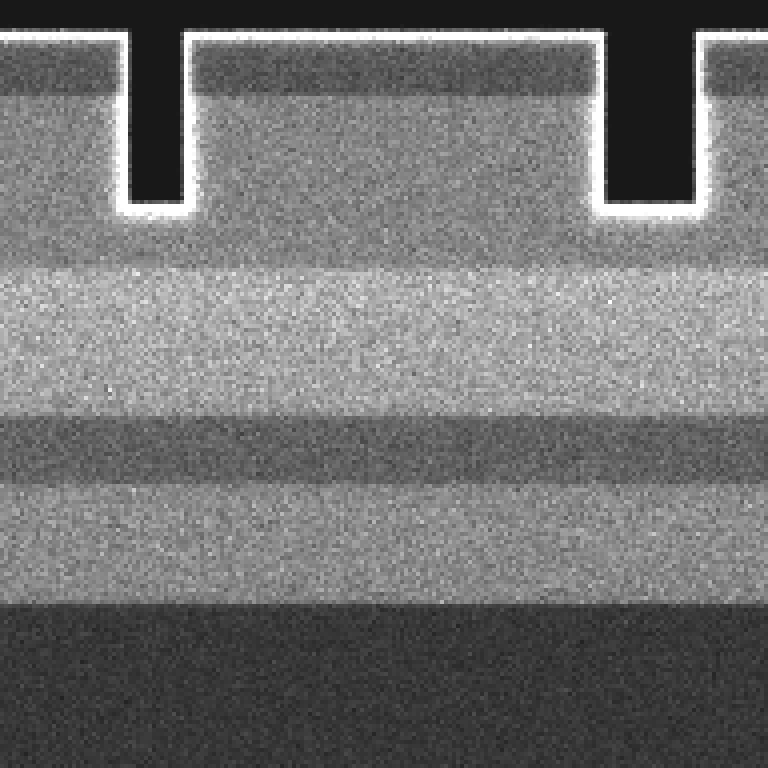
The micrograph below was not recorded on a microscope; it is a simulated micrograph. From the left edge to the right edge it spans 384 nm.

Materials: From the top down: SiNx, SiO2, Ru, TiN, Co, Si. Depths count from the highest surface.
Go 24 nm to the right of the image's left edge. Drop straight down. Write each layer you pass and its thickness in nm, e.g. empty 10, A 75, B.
SiNx 32, SiO2 86, Ru 74, TiN 34, Co 60, Si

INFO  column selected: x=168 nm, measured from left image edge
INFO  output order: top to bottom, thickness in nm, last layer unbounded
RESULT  SiNx 32, SiO2 86, Ru 74, TiN 34, Co 60, Si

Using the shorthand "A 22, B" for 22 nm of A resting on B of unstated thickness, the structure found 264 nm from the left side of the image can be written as SiNx 32, SiO2 86, Ru 74, TiN 34, Co 60, Si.